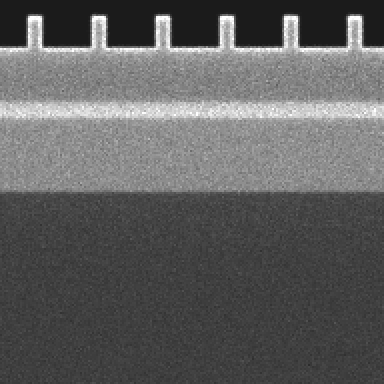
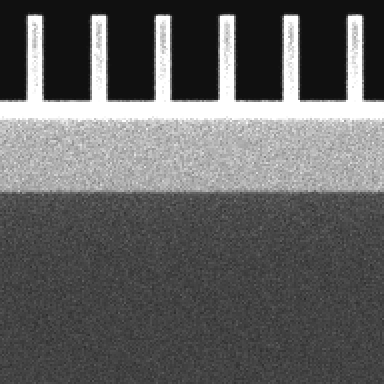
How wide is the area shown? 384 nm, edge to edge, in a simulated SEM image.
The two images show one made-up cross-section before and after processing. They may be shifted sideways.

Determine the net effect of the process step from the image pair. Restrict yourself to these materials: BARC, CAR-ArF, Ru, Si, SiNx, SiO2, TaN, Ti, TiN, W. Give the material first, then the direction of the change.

TiN: removed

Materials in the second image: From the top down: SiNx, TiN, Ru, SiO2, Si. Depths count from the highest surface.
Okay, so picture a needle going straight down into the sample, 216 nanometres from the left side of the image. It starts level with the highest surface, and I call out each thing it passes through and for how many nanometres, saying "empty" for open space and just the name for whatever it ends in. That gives empty 86, Ru 16, SiO2 74, Si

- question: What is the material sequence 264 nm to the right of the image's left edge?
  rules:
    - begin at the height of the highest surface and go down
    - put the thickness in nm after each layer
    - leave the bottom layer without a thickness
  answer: empty 86, Ru 16, SiO2 74, Si